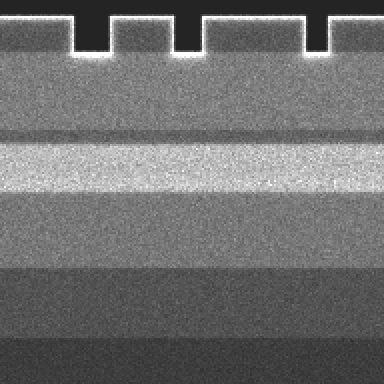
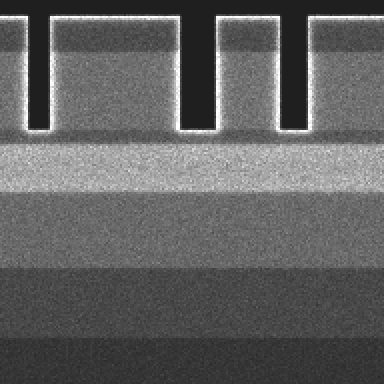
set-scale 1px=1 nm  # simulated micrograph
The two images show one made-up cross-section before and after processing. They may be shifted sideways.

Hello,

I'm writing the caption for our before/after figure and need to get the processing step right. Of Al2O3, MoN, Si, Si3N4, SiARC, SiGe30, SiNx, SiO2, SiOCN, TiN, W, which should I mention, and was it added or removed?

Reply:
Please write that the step removed Al2O3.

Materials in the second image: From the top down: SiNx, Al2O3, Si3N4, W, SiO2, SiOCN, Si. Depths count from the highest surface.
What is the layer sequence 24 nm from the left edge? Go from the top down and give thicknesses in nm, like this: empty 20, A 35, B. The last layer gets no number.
SiNx 36, Al2O3 78, Si3N4 14, W 48, SiO2 76, SiOCN 70, Si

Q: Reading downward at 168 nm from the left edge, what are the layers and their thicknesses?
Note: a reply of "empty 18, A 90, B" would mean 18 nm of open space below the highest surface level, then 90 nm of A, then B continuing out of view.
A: SiNx 36, Al2O3 78, Si3N4 14, W 48, SiO2 76, SiOCN 70, Si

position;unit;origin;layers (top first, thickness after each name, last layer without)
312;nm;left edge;SiNx 36, Al2O3 78, Si3N4 14, W 48, SiO2 76, SiOCN 70, Si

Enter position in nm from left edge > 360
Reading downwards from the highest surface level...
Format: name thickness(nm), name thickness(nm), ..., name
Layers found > SiNx 36, Al2O3 78, Si3N4 14, W 48, SiO2 76, SiOCN 70, Si